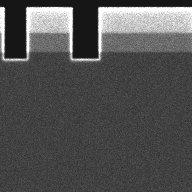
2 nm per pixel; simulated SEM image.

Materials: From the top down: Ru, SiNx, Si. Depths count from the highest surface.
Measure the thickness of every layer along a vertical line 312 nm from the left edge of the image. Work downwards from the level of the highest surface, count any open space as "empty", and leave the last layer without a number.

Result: Ru 50, SiNx 38, Si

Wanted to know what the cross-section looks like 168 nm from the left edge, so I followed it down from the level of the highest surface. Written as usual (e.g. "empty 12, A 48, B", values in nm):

empty 102, Si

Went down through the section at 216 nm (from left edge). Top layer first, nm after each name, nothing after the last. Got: Ru 50, SiNx 38, Si